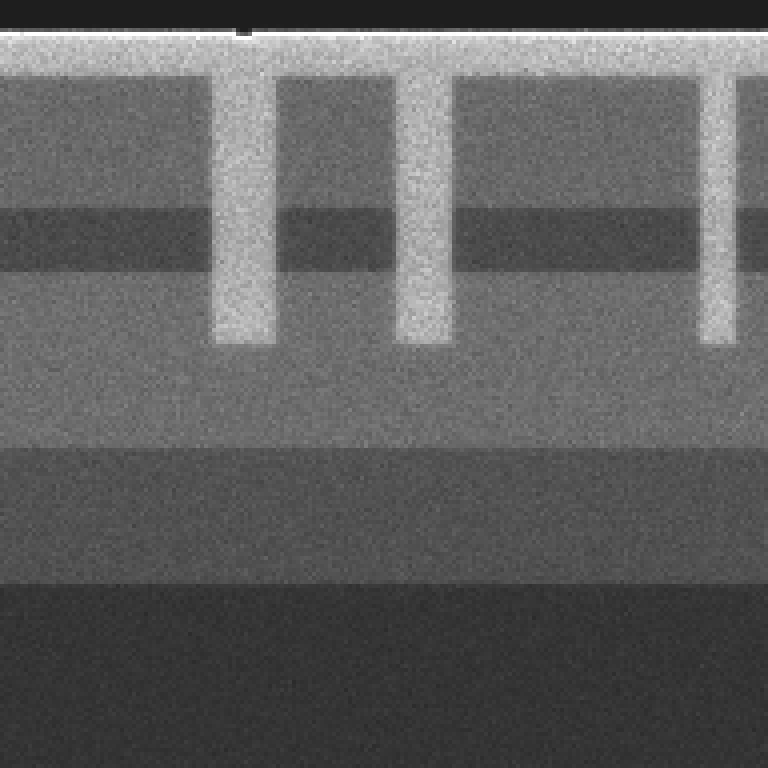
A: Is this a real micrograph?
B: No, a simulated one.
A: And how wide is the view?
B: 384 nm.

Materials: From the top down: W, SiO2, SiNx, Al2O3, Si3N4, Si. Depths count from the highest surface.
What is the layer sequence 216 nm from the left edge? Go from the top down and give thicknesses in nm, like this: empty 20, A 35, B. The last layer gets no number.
W 156, Al2O3 52, Si3N4 68, Si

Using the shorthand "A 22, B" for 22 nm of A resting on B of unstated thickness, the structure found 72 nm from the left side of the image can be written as W 22, SiO2 66, SiNx 32, Al2O3 88, Si3N4 68, Si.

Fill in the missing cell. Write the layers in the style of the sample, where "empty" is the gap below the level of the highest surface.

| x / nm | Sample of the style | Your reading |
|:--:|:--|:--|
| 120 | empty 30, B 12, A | empty 2, W 154, Al2O3 52, Si3N4 68, Si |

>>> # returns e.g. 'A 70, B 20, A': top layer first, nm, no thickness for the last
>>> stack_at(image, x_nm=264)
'W 22, SiO2 66, SiNx 32, Al2O3 88, Si3N4 68, Si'